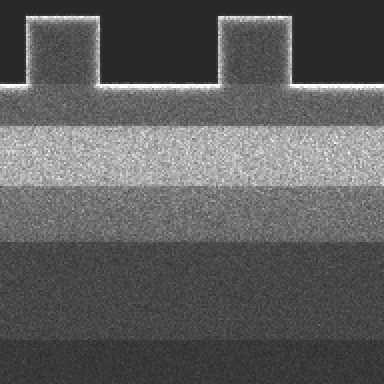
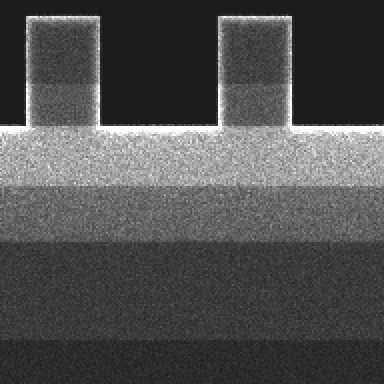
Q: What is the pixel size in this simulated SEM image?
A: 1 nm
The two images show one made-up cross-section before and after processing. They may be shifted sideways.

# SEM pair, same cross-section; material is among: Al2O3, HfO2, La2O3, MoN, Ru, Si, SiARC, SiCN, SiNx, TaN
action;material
removed;Al2O3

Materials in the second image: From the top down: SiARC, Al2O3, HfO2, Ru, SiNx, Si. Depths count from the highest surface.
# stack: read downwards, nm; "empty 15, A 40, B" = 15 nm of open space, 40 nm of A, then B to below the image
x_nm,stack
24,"empty 110, HfO2 60, Ru 56, SiNx 98, Si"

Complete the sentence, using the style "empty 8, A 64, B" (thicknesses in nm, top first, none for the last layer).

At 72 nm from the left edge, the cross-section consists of SiARC 68, Al2O3 42, HfO2 60, Ru 56, SiNx 98, Si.